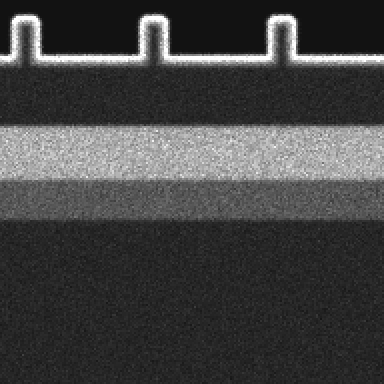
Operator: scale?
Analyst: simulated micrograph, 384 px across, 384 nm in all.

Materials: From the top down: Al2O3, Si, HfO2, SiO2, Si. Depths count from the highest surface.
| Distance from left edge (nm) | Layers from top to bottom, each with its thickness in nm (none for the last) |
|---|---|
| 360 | empty 40, Al2O3 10, Si 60, HfO2 54, SiO2 40, Si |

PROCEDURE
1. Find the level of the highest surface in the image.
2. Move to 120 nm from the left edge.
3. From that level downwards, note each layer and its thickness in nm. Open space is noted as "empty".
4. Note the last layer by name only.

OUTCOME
empty 40, Al2O3 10, Si 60, HfO2 54, SiO2 40, Si